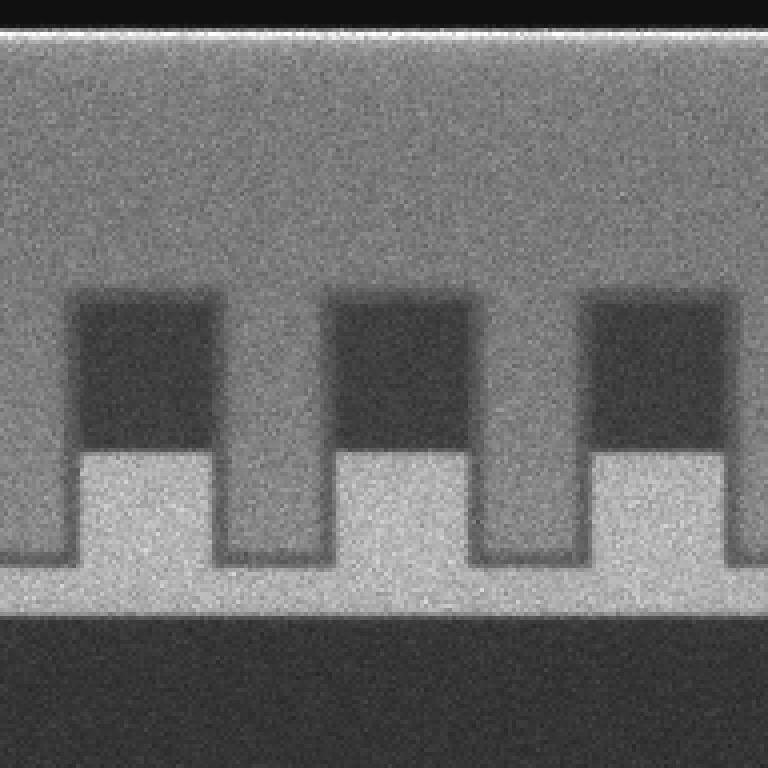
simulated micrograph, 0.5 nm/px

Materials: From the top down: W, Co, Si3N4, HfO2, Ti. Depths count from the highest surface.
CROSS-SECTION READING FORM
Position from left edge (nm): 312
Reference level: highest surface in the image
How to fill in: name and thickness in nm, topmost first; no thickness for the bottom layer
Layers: W 128, Co 8, Si3N4 74, HfO2 82, Ti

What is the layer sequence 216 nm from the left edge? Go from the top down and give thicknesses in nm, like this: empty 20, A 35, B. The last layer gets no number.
W 128, Co 8, Si3N4 74, HfO2 82, Ti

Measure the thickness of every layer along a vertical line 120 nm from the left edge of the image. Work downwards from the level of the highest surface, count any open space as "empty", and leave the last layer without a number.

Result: W 260, Co 8, HfO2 24, Ti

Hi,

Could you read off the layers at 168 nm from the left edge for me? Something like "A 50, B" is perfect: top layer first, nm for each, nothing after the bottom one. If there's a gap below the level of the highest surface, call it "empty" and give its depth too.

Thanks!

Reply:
W 128, Co 8, Si3N4 74, HfO2 82, Ti